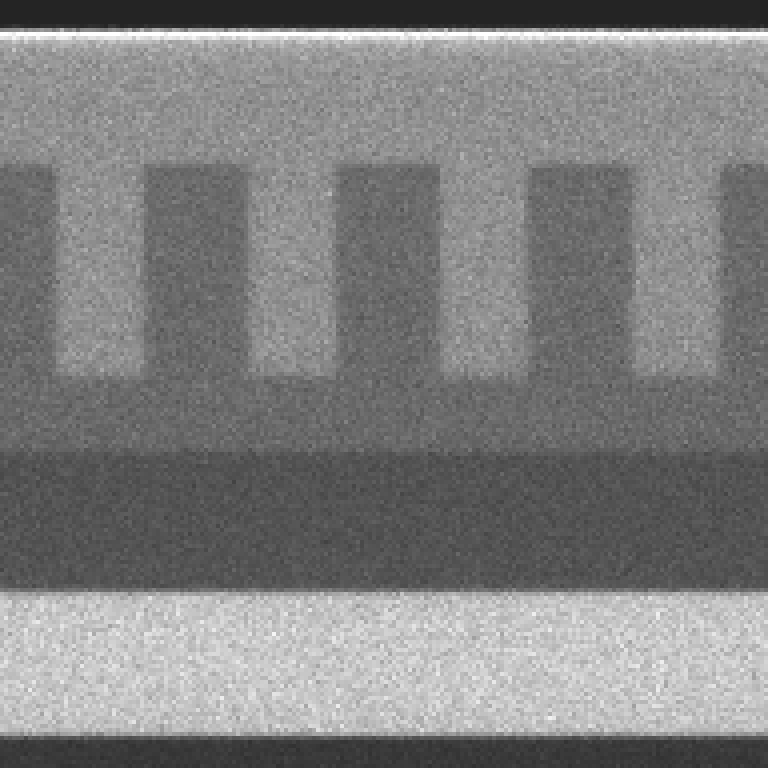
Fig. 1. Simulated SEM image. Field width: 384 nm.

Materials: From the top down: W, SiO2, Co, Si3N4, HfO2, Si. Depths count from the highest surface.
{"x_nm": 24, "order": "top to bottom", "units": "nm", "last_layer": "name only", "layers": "W 66, SiO2 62, Co 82, Si3N4 70, HfO2 72, Si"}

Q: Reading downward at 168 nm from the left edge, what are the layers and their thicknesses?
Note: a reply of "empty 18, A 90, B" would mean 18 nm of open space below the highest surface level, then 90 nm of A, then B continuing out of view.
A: W 66, SiO2 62, Co 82, Si3N4 70, HfO2 72, Si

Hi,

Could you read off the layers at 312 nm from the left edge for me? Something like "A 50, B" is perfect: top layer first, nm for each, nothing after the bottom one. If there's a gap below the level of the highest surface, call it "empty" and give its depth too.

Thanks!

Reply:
W 66, SiO2 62, Co 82, Si3N4 70, HfO2 72, Si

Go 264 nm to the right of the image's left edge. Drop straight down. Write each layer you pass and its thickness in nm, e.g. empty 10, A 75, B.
W 66, SiO2 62, Co 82, Si3N4 70, HfO2 72, Si